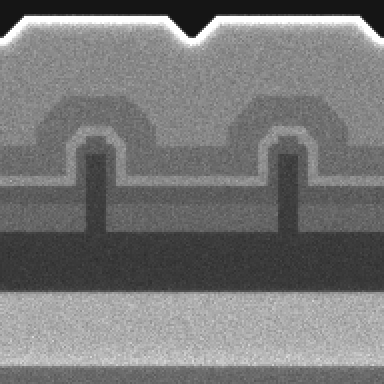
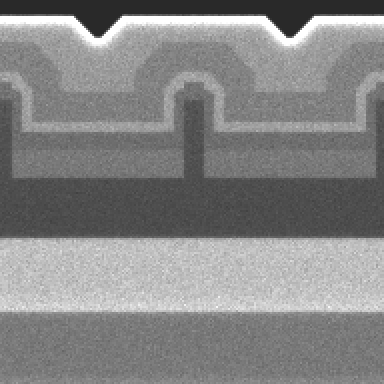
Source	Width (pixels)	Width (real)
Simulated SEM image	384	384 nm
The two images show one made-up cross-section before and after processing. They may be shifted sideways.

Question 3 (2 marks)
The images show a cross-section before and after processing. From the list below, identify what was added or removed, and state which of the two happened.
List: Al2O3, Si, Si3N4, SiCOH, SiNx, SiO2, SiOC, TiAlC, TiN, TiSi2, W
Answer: SiO2 was removed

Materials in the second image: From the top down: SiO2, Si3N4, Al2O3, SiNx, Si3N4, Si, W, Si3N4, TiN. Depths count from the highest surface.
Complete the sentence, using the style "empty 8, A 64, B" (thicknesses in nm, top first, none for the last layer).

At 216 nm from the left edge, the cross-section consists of SiO2 26, Si3N4 40, Al2O3 50, SiNx 18, Si3N4 28, Si 60, W 74, Si3N4 66, TiN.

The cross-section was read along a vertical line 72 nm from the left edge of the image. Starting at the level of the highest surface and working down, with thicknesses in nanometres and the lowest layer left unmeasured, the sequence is SiO2 76, Si3N4 30, Al2O3 10, SiNx 18, Si3N4 28, Si 60, W 74, Si3N4 66, TiN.